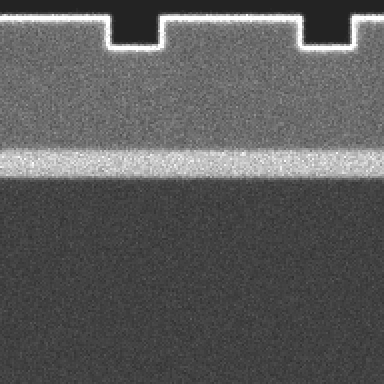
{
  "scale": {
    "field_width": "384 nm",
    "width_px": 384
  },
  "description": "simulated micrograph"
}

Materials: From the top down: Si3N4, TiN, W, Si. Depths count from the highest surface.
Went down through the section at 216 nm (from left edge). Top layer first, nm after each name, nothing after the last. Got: Si3N4 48, TiN 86, W 28, Si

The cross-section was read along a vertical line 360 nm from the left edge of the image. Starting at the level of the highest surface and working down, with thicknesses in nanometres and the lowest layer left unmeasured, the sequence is Si3N4 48, TiN 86, W 28, Si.